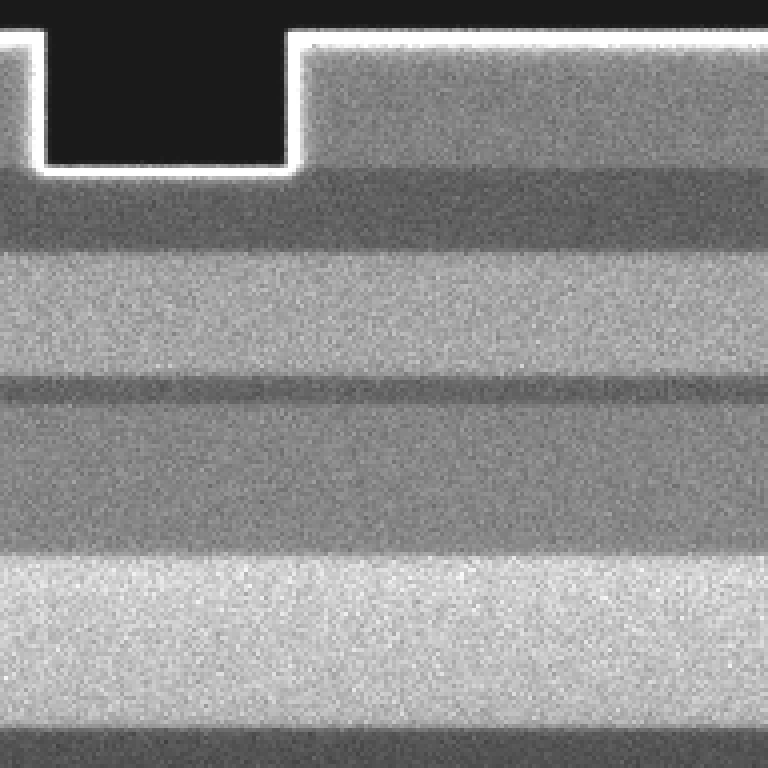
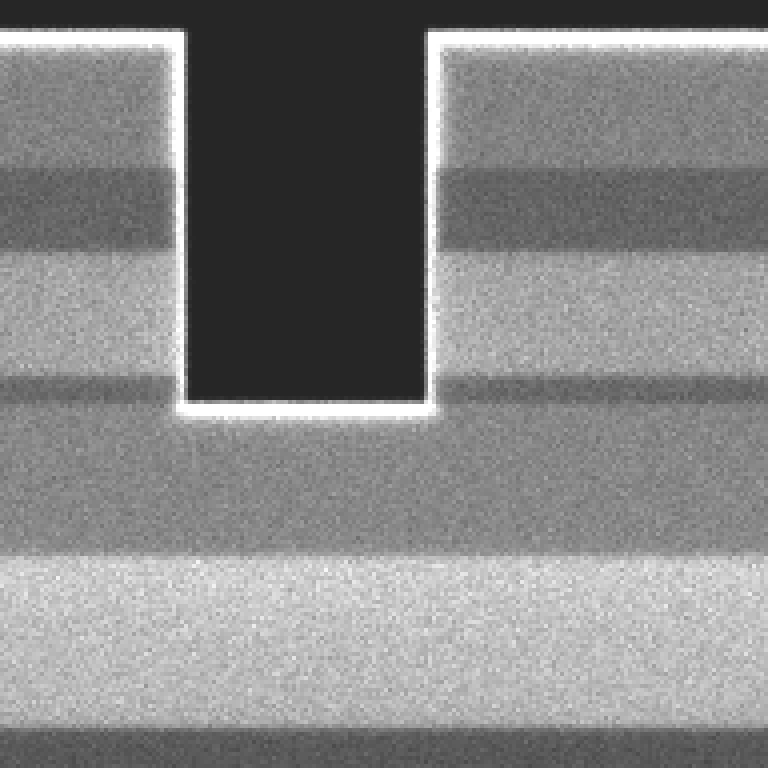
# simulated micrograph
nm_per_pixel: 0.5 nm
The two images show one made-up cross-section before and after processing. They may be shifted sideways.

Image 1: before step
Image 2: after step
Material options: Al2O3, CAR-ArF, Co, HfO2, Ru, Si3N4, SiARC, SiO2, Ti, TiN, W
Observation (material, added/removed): Ru and Si3N4 and TiN, removed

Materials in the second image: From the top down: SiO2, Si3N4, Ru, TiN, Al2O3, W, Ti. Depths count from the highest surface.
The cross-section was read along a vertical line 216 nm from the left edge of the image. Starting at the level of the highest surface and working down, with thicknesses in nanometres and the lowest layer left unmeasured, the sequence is SiO2 68, Si3N4 42, Ru 62, TiN 14, Al2O3 76, W 86, Ti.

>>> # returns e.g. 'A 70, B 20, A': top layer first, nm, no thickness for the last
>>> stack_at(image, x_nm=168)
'empty 186, Al2O3 76, W 86, Ti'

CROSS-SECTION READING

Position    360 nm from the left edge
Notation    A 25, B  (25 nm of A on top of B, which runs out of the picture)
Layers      SiO2 68, Si3N4 42, Ru 62, TiN 14, Al2O3 76, W 86, Ti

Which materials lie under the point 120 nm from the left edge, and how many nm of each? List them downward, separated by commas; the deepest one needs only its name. empty 186, Al2O3 76, W 86, Ti